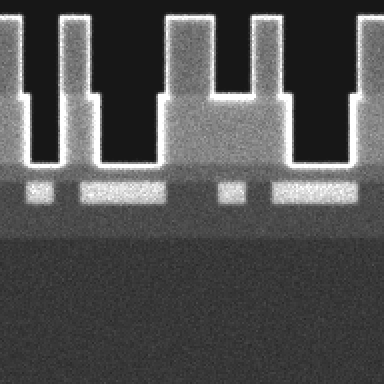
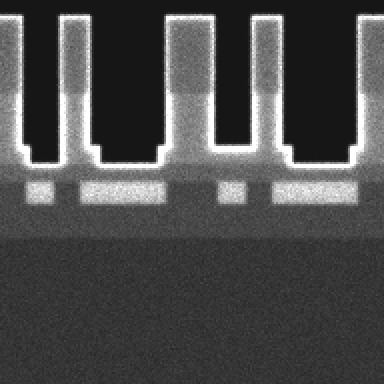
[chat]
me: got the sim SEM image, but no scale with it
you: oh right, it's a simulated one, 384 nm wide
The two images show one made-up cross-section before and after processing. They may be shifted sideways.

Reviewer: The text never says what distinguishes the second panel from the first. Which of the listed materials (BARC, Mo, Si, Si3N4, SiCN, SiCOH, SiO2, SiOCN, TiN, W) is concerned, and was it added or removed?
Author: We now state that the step removed SiO2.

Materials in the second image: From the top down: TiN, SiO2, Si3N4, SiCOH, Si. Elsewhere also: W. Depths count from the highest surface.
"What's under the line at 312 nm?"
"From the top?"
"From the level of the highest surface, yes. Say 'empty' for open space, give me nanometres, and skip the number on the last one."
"empty 148, Si3N4 18, W 22, SiCOH 34, Si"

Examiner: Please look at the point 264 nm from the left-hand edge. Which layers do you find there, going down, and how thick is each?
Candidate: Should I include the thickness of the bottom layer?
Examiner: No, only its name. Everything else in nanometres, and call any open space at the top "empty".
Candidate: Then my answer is TiN 78, SiO2 70, Si3N4 18, SiCOH 56, Si